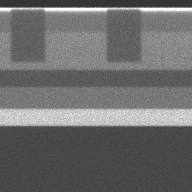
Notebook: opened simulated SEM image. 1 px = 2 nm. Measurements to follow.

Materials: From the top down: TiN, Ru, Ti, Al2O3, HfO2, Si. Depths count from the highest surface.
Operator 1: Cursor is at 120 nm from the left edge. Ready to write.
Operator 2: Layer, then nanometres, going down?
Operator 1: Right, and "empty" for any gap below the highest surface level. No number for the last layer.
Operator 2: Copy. Al2O3 48, Ru 76, Ti 34, Al2O3 44, HfO2 34, Si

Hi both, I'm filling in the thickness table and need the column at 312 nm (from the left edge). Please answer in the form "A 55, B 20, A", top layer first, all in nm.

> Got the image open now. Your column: Al2O3 48, Ru 76, Ti 34, Al2O3 44, HfO2 34, Si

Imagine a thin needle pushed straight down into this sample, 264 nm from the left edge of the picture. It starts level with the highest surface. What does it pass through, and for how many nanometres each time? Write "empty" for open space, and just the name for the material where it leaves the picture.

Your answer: TiN 108, Ru 16, Ti 34, Al2O3 44, HfO2 34, Si